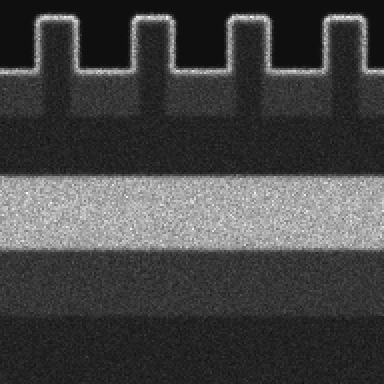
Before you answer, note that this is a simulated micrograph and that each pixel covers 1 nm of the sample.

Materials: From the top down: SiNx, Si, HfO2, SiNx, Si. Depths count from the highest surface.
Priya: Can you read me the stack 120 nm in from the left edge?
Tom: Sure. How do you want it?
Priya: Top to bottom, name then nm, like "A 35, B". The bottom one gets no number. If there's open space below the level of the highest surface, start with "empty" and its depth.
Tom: empty 54, SiNx 46, Si 60, HfO2 74, SiNx 66, Si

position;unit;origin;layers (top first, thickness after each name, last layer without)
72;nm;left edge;SiNx 100, Si 60, HfO2 74, SiNx 66, Si